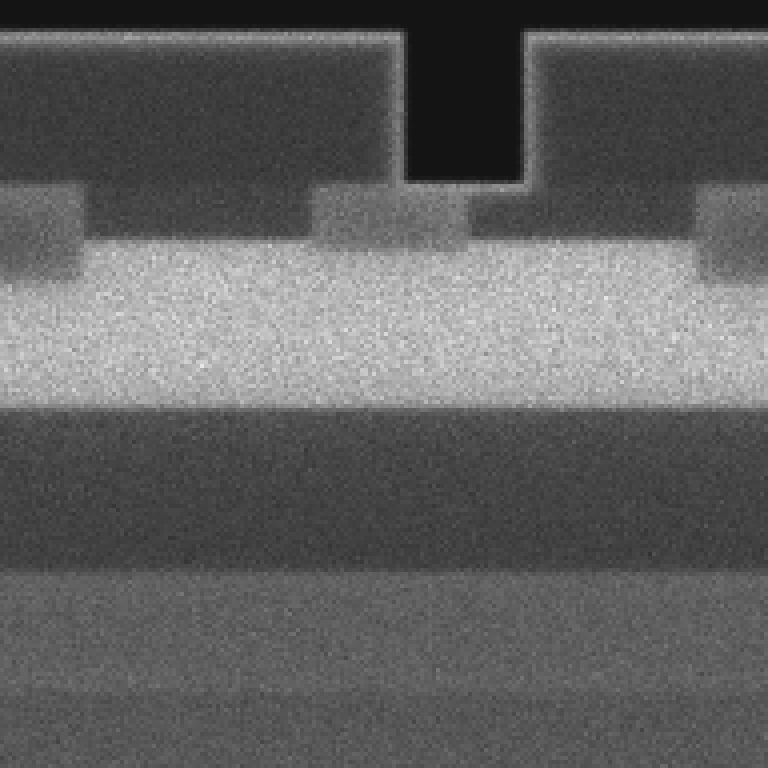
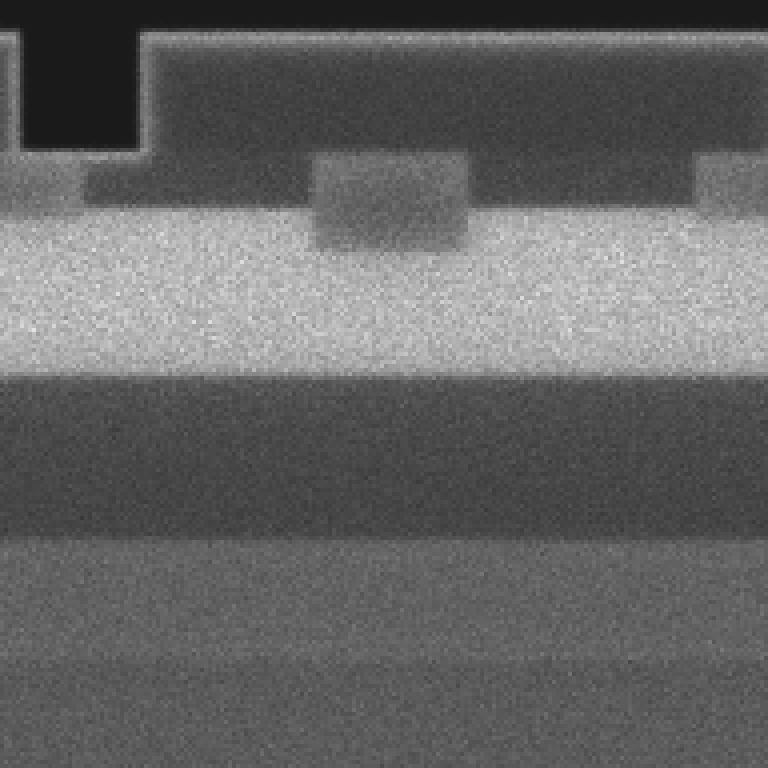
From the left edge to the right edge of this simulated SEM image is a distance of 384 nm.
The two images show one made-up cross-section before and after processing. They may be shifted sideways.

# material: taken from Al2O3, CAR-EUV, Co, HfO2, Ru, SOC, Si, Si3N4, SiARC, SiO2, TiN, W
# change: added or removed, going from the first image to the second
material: SiARC
change: removed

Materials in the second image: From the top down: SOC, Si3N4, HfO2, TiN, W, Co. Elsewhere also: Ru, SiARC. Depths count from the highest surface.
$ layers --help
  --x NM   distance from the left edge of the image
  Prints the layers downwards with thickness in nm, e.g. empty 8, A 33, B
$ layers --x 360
SOC 60, Ru 34, HfO2 78, TiN 82, W 60, Co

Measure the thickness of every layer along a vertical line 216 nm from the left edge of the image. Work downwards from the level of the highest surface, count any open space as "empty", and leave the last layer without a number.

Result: SOC 60, Ru 50, HfO2 62, TiN 82, W 60, Co